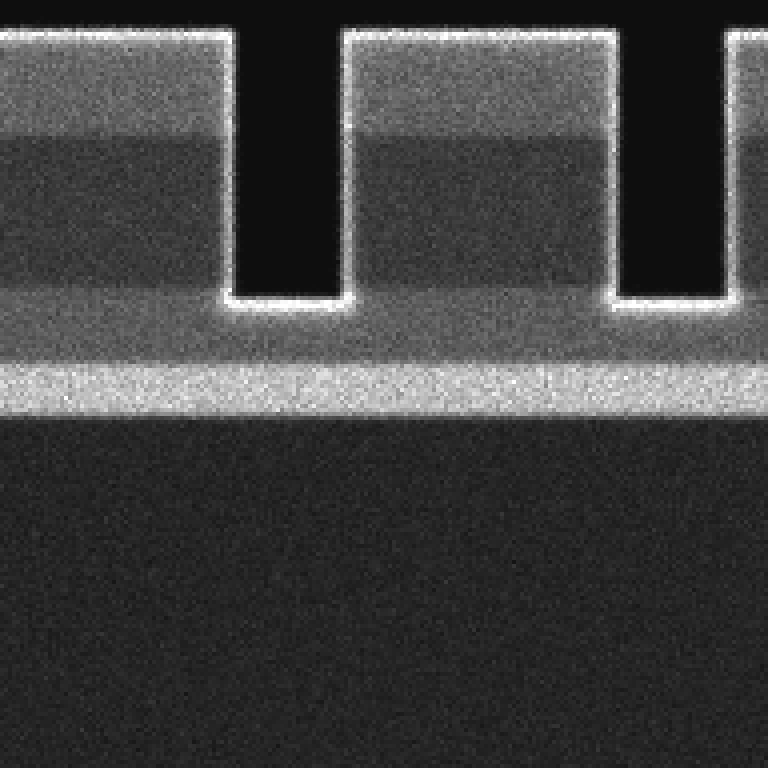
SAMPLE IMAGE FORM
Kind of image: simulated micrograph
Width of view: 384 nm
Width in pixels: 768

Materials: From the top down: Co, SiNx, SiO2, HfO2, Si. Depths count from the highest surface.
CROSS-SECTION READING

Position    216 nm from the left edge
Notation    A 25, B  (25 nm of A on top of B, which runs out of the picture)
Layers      Co 52, SiNx 76, SiO2 38, HfO2 26, Si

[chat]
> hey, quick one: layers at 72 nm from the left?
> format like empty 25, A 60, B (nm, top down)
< Co 52, SiNx 76, SiO2 38, HfO2 26, Si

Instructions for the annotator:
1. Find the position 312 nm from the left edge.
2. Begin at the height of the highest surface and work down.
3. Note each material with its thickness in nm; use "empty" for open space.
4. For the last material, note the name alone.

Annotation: empty 134, SiO2 32, HfO2 26, Si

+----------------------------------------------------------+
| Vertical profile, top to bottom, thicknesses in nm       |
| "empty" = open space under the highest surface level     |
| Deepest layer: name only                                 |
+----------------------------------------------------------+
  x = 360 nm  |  empty 134, SiO2 32, HfO2 26, Si